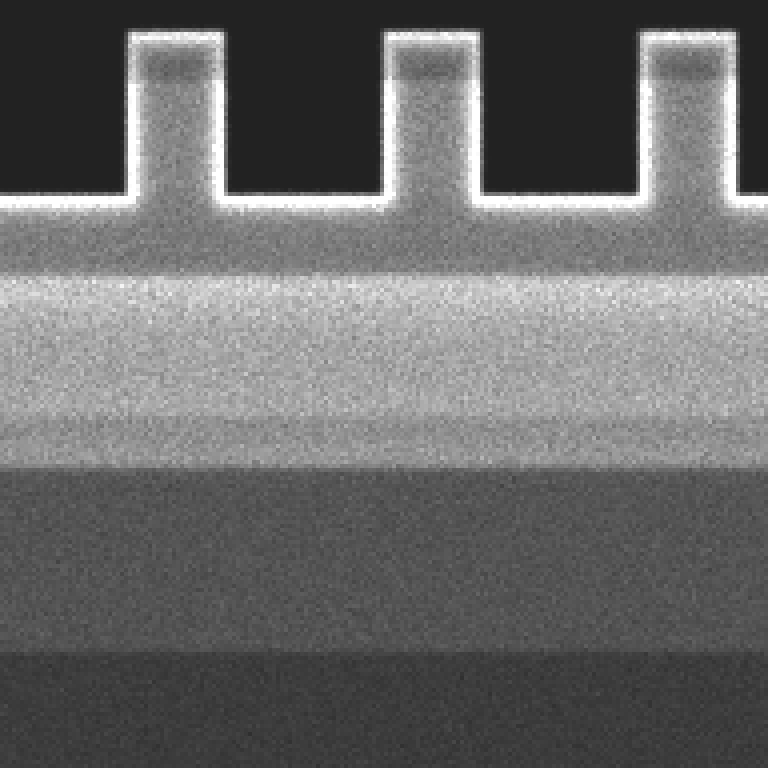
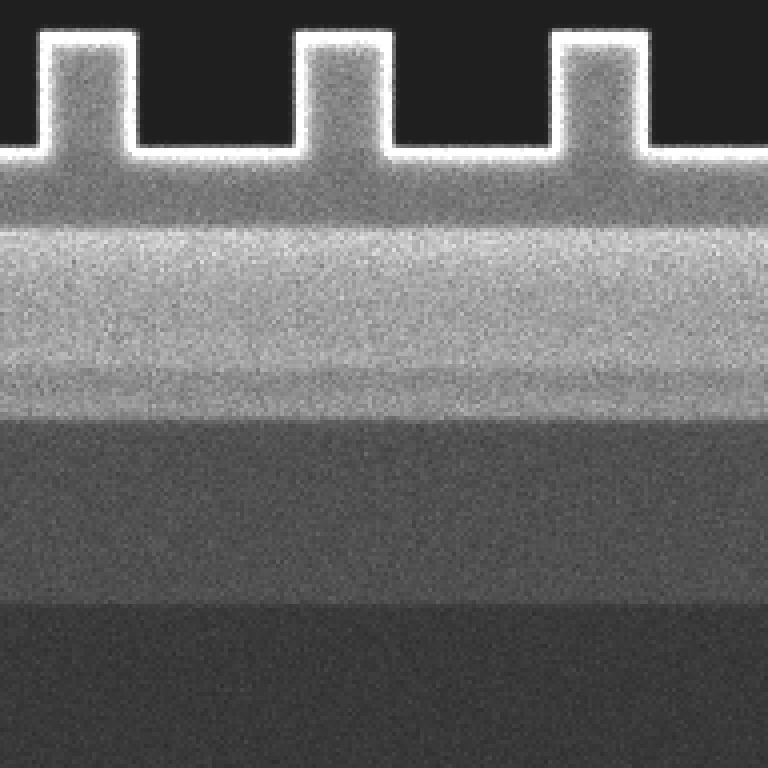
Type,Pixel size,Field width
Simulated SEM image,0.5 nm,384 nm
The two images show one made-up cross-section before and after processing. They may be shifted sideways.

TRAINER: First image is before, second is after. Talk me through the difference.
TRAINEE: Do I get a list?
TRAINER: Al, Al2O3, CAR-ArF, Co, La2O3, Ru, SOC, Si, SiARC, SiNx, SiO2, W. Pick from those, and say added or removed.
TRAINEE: removed: SOC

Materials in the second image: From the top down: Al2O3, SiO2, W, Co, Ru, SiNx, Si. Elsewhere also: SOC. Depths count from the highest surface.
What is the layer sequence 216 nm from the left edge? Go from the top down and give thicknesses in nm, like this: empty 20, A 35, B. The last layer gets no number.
empty 58, SiO2 40, W 70, Co 14, Ru 12, SiNx 92, Si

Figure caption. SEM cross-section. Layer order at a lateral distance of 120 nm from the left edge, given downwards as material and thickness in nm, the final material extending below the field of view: empty 58, SiO2 40, W 70, Co 14, Ru 12, SiNx 92, Si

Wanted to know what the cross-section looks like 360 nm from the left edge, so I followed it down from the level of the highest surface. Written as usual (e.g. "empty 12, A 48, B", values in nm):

empty 58, SiO2 40, W 70, Co 14, Ru 12, SiNx 92, Si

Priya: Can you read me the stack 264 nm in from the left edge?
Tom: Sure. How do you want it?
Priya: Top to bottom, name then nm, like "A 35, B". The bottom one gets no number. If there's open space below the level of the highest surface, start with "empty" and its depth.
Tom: empty 58, SiO2 40, W 70, Co 14, Ru 12, SiNx 92, Si